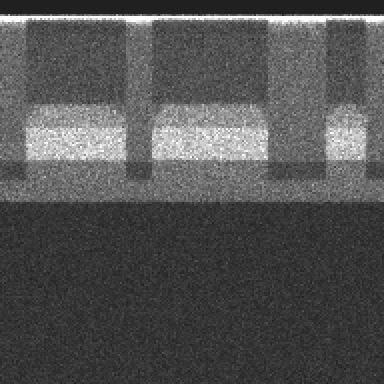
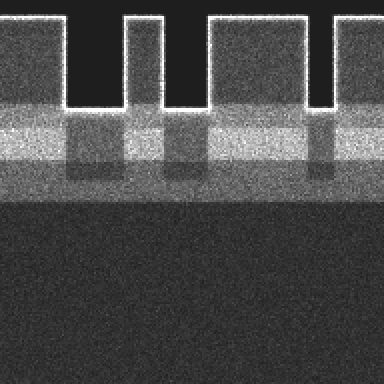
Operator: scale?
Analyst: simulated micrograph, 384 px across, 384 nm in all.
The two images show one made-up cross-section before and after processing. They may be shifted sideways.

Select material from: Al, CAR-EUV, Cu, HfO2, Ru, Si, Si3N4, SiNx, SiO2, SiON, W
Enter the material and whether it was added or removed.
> SiO2 / removed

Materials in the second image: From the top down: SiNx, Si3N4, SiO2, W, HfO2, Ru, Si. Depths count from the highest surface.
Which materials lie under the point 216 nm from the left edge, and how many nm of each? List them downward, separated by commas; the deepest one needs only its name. SiNx 18, Si3N4 70, SiO2 6, W 18, HfO2 32, Ru 42, Si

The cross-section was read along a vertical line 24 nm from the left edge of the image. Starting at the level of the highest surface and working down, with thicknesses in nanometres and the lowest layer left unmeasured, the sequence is SiNx 18, Si3N4 70, W 24, HfO2 32, Ru 42, Si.